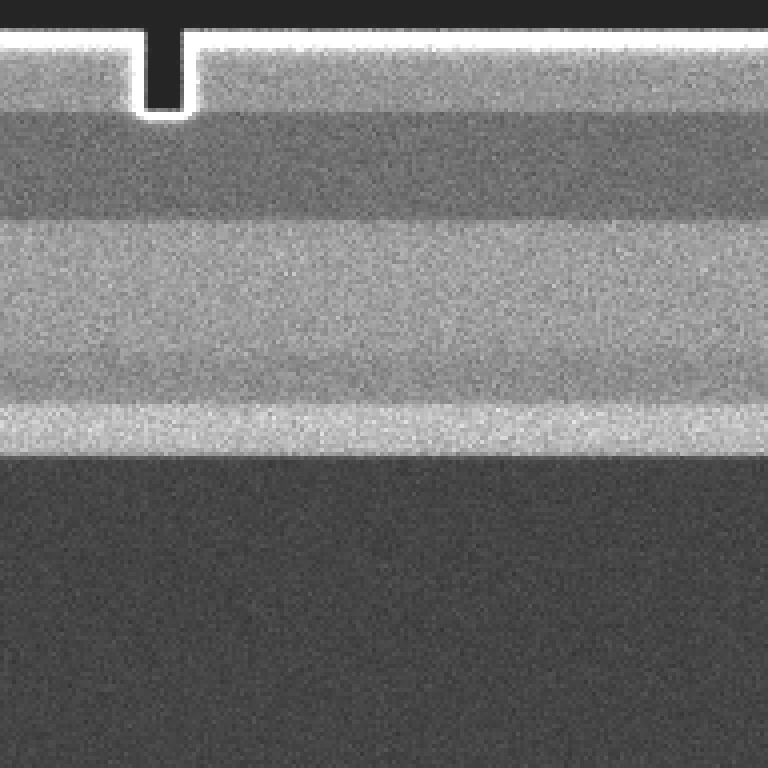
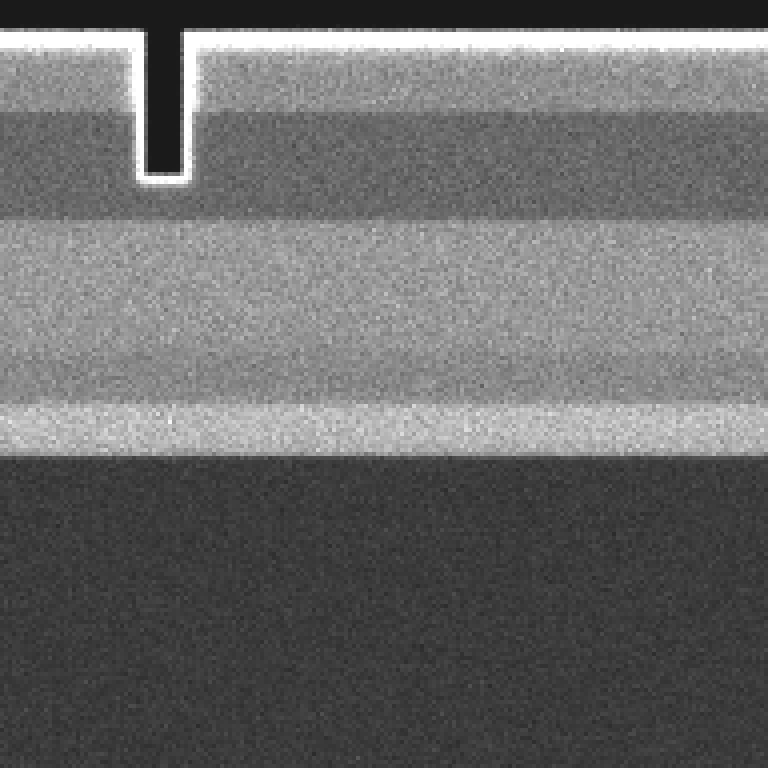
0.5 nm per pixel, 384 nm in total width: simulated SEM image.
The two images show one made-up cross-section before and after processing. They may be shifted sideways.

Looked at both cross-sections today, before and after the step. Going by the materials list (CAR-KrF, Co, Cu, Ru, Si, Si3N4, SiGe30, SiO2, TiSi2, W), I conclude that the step removed Si3N4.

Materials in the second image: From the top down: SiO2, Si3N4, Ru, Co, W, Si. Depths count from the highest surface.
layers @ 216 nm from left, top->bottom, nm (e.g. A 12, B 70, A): SiO2 40, Si3N4 54, Ru 66, Co 26, W 26, Si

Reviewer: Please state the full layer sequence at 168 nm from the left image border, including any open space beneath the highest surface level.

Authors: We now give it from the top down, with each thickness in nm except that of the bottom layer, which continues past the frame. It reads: SiO2 40, Si3N4 54, Ru 66, Co 26, W 26, Si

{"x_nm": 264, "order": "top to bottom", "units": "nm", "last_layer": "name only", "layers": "SiO2 40, Si3N4 54, Ru 66, Co 26, W 26, Si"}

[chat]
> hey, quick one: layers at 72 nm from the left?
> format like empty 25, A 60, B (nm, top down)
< empty 72, Si3N4 22, Ru 66, Co 26, W 26, Si